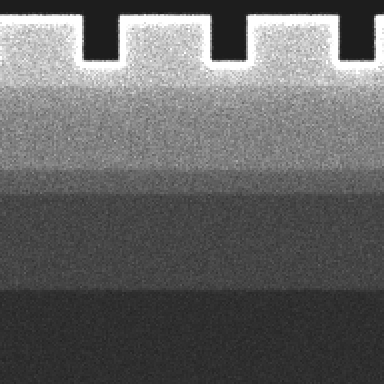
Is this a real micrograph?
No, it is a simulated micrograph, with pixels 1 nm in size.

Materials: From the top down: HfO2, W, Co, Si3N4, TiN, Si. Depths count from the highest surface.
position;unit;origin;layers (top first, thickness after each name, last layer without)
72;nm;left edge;HfO2 70, W 84, Co 24, Si3N4 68, TiN 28, Si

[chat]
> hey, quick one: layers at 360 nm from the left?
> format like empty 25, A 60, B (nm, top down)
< empty 46, HfO2 24, W 84, Co 24, Si3N4 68, TiN 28, Si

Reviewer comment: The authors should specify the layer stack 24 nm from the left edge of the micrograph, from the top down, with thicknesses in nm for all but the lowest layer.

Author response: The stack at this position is HfO2 70, W 84, Co 24, Si3N4 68, TiN 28, Si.